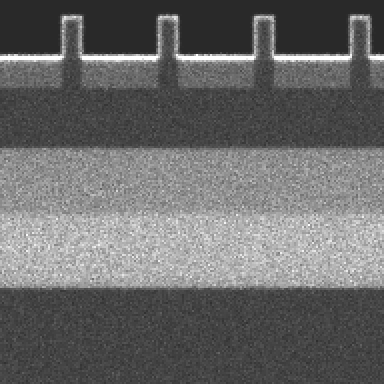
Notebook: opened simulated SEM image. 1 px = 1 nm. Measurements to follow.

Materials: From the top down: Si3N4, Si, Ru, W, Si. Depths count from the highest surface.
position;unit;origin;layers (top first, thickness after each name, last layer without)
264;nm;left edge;Si 132, Ru 66, W 74, Si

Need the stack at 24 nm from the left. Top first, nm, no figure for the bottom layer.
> empty 40, Si3N4 32, Si 60, Ru 66, W 74, Si